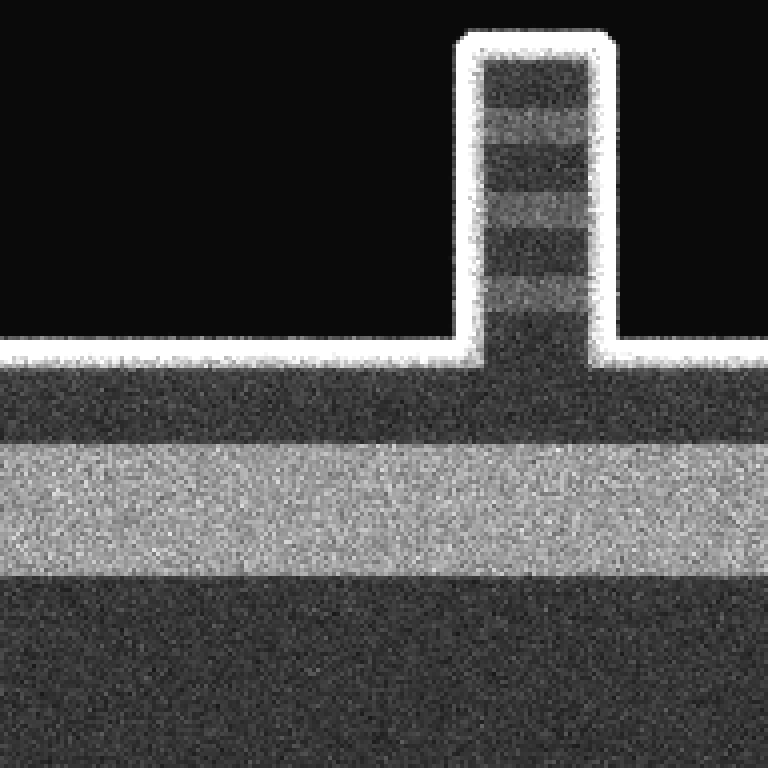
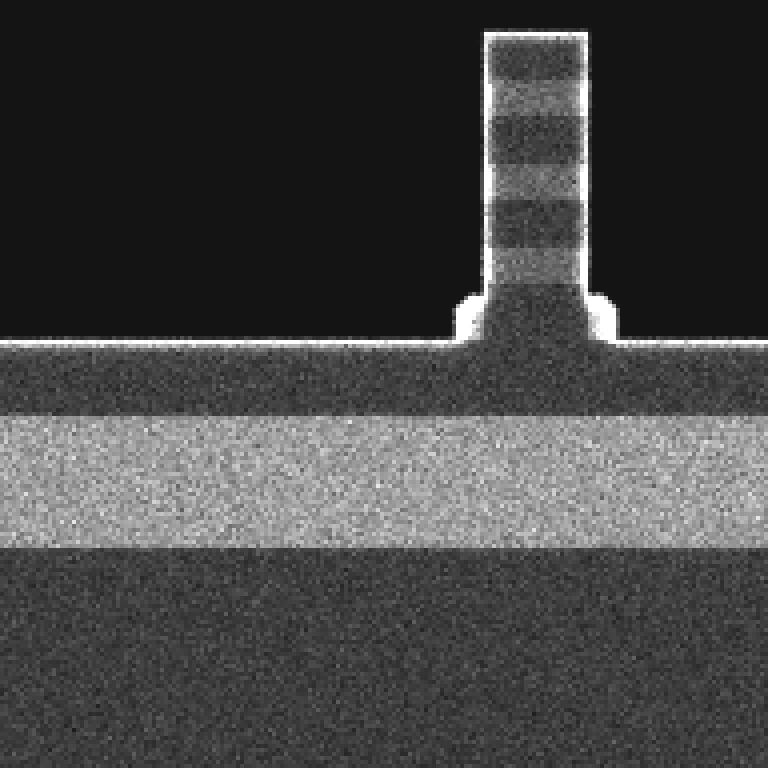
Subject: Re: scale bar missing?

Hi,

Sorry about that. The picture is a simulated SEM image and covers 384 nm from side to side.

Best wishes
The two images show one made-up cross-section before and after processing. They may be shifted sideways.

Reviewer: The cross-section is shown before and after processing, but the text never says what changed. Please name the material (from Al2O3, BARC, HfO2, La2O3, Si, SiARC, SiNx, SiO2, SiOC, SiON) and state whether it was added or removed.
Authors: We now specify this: Al2O3, removed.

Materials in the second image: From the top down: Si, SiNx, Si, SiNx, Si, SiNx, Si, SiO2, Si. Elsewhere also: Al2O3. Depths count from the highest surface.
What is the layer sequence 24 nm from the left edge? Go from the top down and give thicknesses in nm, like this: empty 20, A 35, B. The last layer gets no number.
empty 154, Si 38, SiO2 66, Si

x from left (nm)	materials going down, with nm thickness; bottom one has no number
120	empty 154, Si 38, SiO2 66, Si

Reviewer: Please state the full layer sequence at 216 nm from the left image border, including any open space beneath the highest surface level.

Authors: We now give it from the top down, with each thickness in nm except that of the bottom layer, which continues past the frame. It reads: empty 154, Si 38, SiO2 66, Si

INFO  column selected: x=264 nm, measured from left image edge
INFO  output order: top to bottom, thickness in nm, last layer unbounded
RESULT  Si 24, SiNx 18, Si 24, SiNx 18, Si 24, SiNx 18, Si 66, SiO2 66, Si